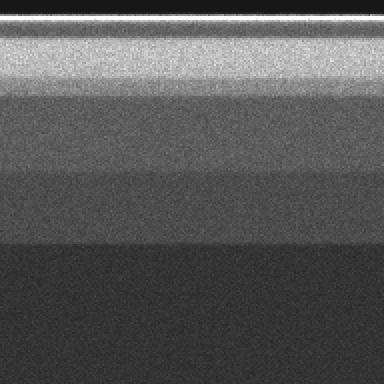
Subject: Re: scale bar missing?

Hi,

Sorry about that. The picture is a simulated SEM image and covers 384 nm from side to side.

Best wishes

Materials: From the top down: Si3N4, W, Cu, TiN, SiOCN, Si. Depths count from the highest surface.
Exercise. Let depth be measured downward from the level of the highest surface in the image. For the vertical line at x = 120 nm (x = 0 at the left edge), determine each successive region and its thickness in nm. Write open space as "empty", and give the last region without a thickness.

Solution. Si3N4 22, W 40, Cu 18, TiN 76, SiOCN 72, Si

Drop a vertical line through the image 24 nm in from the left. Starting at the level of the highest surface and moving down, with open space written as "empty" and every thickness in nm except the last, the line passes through Si3N4 22, W 40, Cu 18, TiN 76, SiOCN 72, Si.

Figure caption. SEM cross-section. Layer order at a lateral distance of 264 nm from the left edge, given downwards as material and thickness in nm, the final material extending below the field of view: Si3N4 22, W 40, Cu 18, TiN 76, SiOCN 72, Si